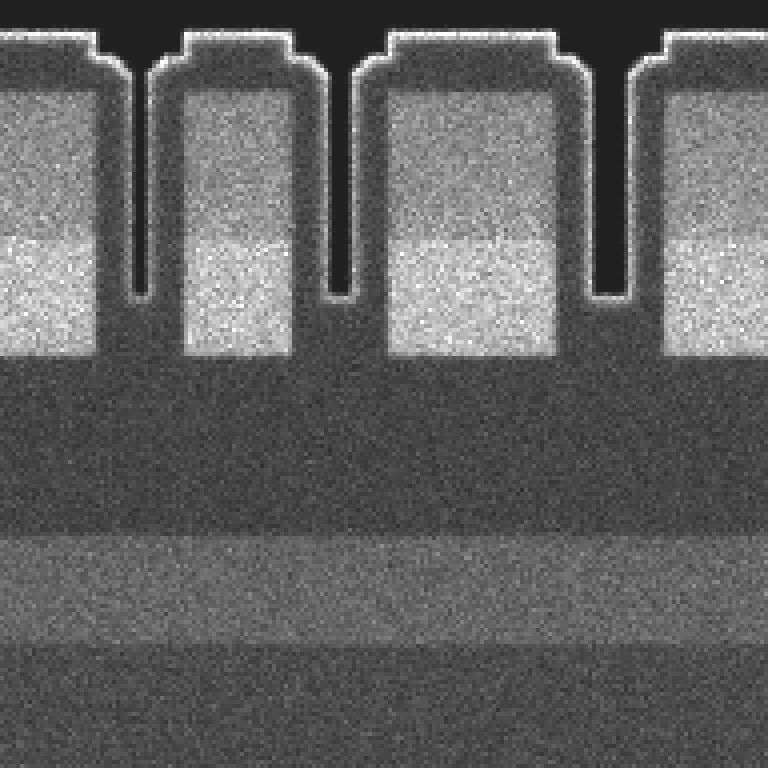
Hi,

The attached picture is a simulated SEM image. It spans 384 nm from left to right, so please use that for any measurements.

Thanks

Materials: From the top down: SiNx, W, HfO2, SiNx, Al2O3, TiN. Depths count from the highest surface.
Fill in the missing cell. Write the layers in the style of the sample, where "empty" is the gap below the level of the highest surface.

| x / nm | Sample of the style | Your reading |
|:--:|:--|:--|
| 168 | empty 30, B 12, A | empty 132, SiNx 120, Al2O3 54, TiN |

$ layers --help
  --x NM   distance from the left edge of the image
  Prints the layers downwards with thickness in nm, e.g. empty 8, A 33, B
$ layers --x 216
SiNx 30, W 74, HfO2 58, SiNx 90, Al2O3 54, TiN